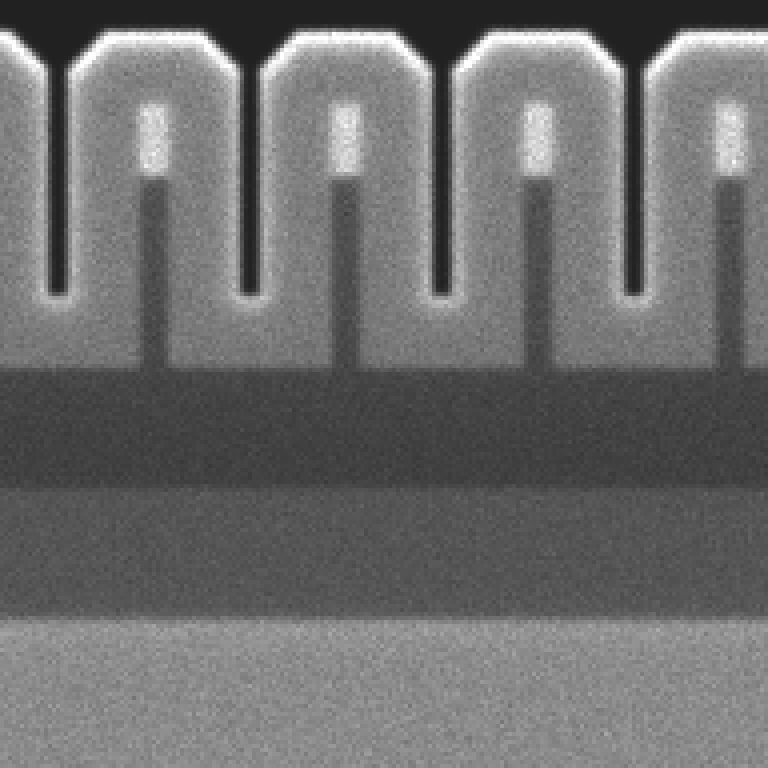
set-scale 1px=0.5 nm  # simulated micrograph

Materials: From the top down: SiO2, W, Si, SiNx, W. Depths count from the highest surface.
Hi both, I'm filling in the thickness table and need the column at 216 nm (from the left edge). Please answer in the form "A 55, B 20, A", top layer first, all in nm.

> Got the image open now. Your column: empty 132, SiO2 36, Si 60, SiNx 66, W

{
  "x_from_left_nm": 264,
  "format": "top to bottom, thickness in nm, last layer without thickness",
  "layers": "SiO2 36, W 36, Si 156, SiNx 66, W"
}